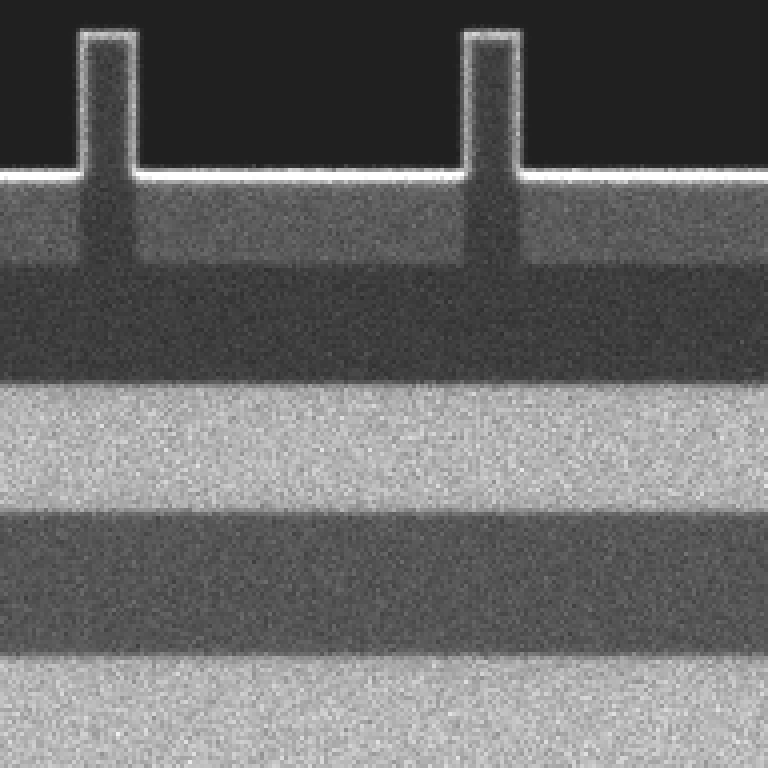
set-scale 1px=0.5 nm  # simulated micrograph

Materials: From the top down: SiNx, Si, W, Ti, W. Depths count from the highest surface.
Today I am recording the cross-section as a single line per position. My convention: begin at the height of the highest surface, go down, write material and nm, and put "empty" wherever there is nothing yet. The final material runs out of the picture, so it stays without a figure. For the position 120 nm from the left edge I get empty 70, SiNx 46, Si 60, W 64, Ti 72, W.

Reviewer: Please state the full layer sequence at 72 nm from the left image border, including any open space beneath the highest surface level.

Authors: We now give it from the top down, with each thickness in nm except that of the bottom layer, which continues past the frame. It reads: empty 70, SiNx 46, Si 60, W 64, Ti 72, W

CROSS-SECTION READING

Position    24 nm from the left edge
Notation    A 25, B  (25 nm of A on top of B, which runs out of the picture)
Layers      empty 70, SiNx 46, Si 60, W 64, Ti 72, W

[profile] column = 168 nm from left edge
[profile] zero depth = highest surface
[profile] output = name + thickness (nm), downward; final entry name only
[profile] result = empty 70, SiNx 46, Si 60, W 64, Ti 72, W